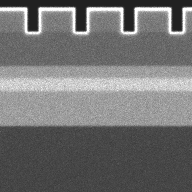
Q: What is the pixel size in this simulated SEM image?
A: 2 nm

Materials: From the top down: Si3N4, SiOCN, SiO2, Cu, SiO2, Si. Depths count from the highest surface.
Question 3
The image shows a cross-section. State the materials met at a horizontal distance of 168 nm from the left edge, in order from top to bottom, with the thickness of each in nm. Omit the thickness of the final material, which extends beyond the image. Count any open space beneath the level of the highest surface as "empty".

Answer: empty 48, SiOCN 68, SiO2 24, Cu 26, SiO2 70, Si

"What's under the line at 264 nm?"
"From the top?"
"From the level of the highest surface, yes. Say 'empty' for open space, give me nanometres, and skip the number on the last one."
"empty 48, SiOCN 68, SiO2 24, Cu 26, SiO2 70, Si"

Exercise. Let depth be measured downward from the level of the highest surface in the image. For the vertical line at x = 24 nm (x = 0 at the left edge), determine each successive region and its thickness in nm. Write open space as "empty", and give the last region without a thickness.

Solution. Si3N4 48, SiOCN 68, SiO2 24, Cu 26, SiO2 70, Si